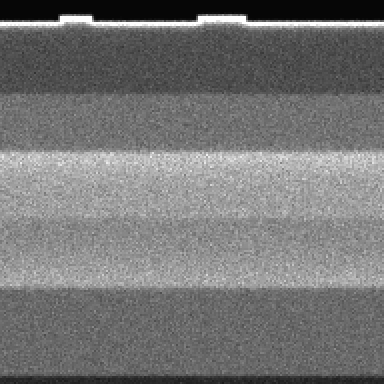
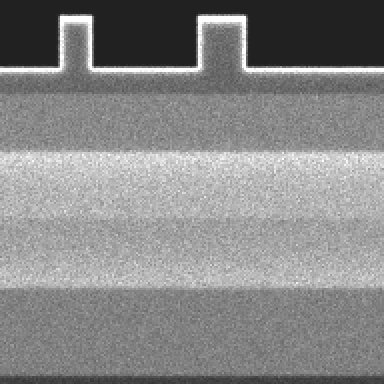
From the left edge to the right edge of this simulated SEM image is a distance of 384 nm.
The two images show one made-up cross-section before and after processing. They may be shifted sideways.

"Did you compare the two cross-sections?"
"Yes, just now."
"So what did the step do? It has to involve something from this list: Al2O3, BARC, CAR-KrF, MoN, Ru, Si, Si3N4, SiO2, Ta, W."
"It removed Si3N4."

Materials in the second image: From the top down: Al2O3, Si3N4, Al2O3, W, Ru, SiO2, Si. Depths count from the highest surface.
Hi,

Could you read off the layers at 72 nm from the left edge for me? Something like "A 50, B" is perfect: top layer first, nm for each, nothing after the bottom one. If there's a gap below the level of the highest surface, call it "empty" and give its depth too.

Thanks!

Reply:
Al2O3 6, Si3N4 72, Al2O3 58, W 66, Ru 70, SiO2 88, Si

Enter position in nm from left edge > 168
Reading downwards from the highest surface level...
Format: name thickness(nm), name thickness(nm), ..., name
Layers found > empty 52, Si3N4 26, Al2O3 58, W 66, Ru 70, SiO2 88, Si